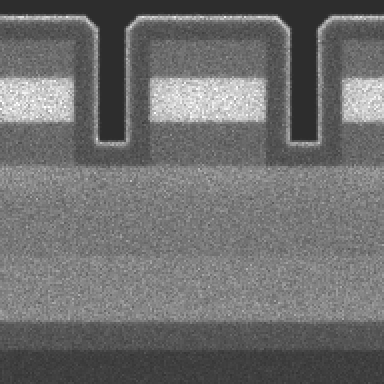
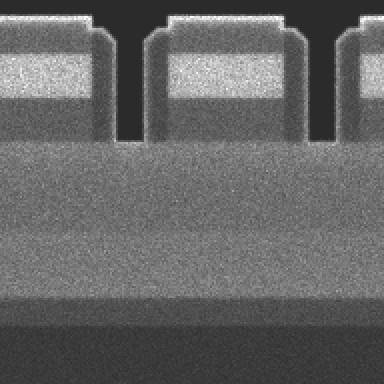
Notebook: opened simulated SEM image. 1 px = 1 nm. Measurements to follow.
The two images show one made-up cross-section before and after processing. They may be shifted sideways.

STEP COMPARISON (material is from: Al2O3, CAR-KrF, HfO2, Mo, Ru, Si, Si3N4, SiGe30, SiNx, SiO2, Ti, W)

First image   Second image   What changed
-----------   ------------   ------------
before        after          SiNx, removed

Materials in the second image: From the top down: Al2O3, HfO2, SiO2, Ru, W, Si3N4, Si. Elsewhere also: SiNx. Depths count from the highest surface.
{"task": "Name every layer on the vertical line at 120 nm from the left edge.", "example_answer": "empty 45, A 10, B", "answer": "empty 126, Ru 90, W 66, Si3N4 28, Si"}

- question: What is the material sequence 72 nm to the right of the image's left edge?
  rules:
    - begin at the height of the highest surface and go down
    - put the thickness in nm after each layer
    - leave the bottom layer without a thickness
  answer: Al2O3 38, HfO2 44, SiO2 44, Ru 90, W 66, Si3N4 28, Si